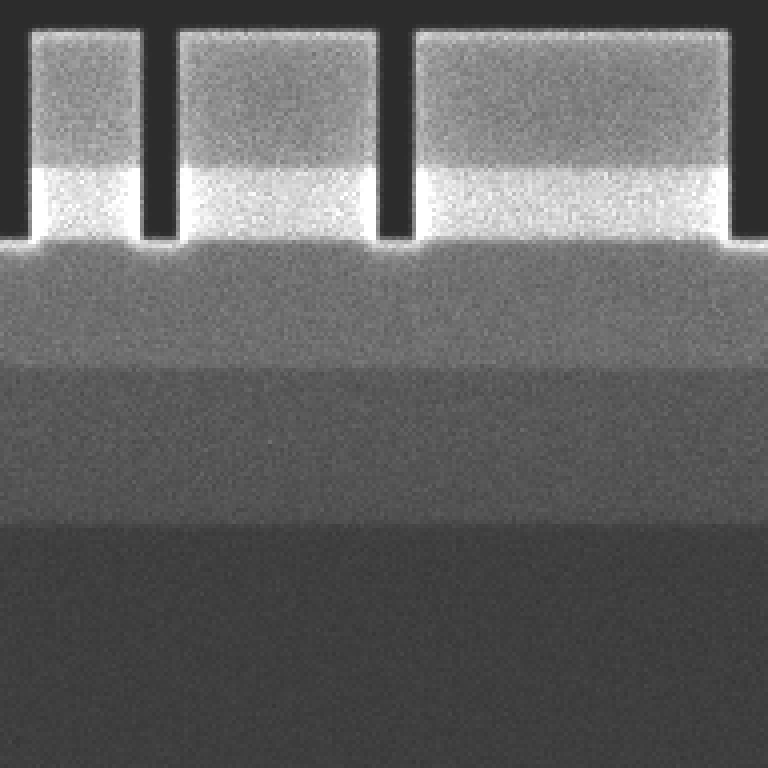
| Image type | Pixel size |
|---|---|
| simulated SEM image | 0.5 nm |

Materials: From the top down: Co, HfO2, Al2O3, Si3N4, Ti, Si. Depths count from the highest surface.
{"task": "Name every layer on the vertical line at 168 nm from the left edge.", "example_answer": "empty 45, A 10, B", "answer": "Co 68, HfO2 36, Al2O3 64, Si3N4 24, Ti 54, Si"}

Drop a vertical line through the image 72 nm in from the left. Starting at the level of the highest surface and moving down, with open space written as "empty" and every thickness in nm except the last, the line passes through empty 104, Al2O3 64, Si3N4 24, Ti 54, Si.